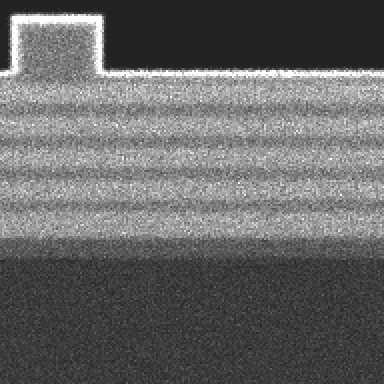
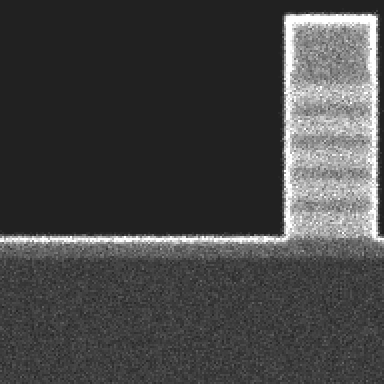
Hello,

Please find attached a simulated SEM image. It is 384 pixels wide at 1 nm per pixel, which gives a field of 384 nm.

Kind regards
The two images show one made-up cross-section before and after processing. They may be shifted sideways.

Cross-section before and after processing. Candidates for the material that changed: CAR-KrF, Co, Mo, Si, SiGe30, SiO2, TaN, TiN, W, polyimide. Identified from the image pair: Co and W (removed).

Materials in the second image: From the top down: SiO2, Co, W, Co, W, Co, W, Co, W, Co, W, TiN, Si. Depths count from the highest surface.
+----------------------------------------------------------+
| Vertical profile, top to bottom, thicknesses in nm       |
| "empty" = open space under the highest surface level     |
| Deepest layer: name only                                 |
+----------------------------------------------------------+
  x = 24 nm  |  empty 222, TiN 20, Si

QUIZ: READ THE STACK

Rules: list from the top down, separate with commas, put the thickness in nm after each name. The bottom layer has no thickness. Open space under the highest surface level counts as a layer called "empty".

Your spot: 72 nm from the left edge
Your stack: empty 222, TiN 20, Si